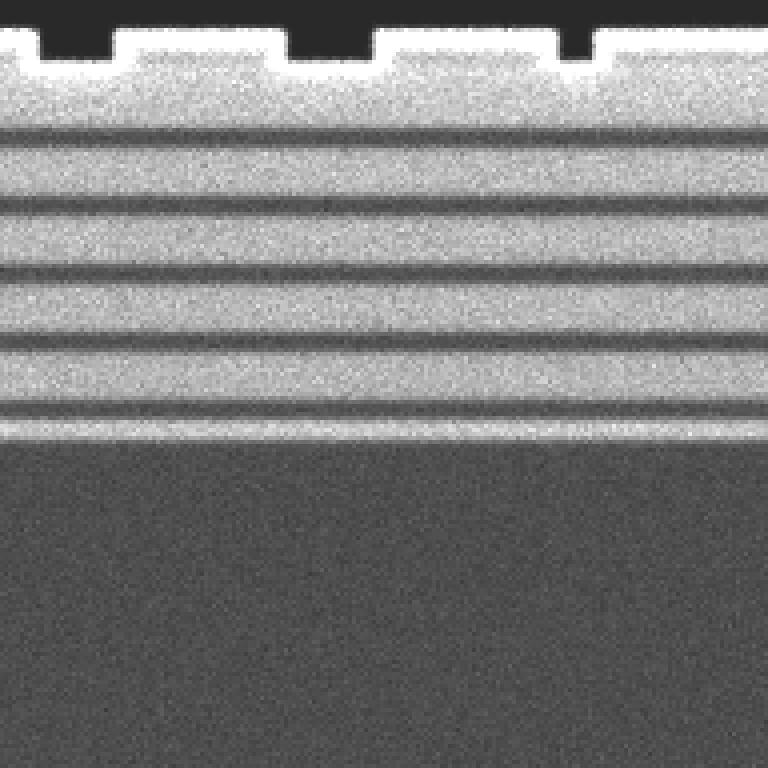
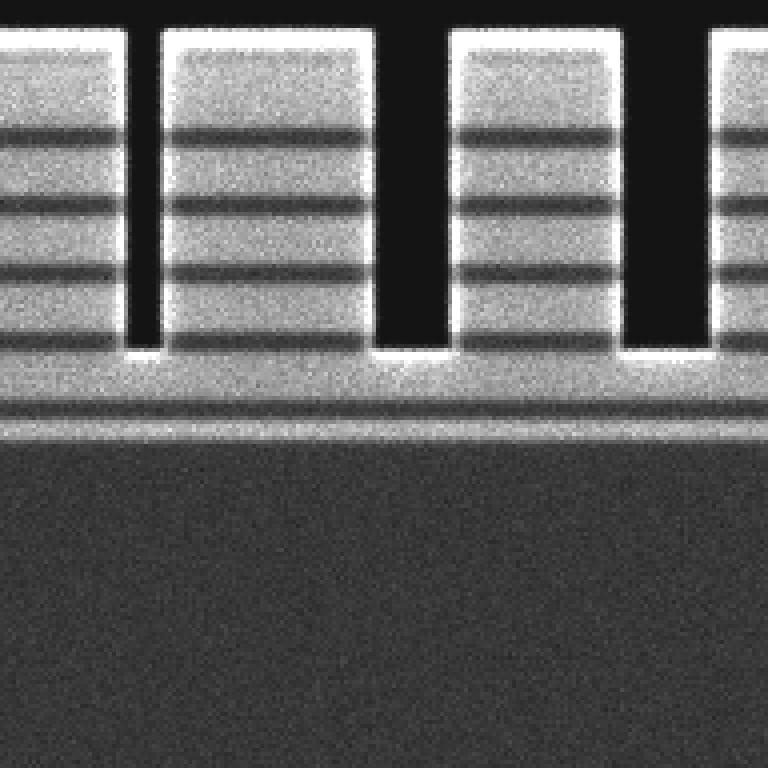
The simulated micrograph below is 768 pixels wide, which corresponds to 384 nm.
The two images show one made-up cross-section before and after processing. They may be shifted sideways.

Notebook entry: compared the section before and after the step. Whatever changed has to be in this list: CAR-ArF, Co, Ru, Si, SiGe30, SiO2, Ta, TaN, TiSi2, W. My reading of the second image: Ru and Si removed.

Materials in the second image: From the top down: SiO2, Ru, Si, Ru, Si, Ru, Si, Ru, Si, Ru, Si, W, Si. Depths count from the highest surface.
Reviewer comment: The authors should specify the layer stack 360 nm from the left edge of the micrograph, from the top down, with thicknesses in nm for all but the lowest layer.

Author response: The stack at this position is SiO2 16, Ru 32, Si 10, Ru 24, Si 10, Ru 24, Si 10, Ru 24, Si 10, Ru 24, Si 10, W 10, Si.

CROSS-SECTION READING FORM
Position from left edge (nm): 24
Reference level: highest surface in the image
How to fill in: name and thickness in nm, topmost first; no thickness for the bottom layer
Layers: SiO2 16, Ru 32, Si 10, Ru 24, Si 10, Ru 24, Si 10, Ru 24, Si 10, Ru 24, Si 10, W 10, Si